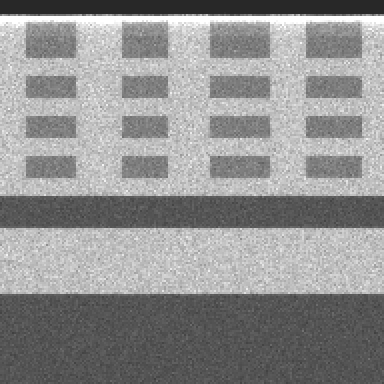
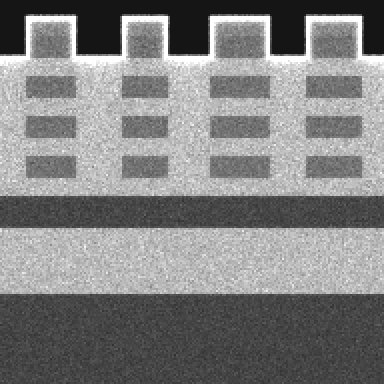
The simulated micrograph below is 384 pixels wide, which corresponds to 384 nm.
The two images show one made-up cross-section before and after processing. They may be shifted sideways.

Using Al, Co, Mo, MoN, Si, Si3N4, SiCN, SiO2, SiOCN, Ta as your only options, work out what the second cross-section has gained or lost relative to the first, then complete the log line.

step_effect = removed Co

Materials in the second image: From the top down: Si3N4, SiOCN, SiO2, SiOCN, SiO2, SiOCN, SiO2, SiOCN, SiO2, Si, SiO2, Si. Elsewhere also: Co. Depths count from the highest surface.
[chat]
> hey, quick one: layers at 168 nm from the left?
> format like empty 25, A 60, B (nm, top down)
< empty 40, Co 140, Si 32, SiO2 66, Si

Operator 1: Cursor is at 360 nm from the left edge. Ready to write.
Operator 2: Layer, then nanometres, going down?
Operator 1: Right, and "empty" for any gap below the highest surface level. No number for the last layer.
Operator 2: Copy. Si3N4 20, SiOCN 22, SiO2 18, SiOCN 22, SiO2 18, SiOCN 22, SiO2 18, SiOCN 22, SiO2 18, Si 32, SiO2 66, Si